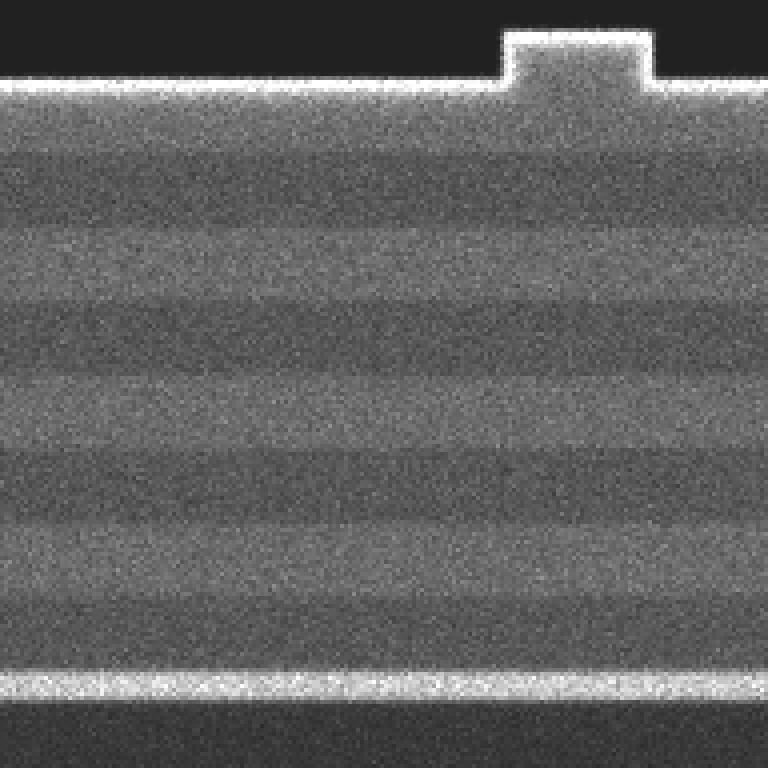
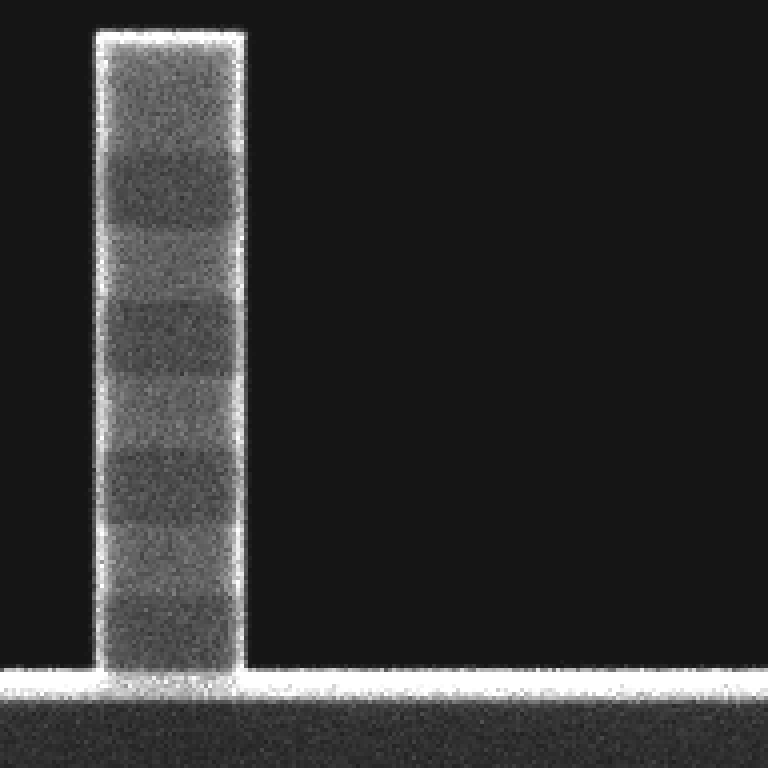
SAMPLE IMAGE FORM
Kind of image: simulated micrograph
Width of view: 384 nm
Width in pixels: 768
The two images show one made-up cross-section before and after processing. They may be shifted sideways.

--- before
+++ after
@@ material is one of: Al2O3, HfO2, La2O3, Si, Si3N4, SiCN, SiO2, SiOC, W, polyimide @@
Si3N4 and SiO2 removed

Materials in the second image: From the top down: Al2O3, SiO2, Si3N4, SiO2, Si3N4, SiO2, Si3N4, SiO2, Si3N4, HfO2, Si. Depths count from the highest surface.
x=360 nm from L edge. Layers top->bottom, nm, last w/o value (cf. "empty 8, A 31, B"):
empty 320, HfO2 14, Si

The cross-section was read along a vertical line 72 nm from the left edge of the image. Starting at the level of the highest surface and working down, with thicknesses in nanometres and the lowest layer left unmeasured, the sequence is Al2O3 24, SiO2 36, Si3N4 38, SiO2 36, Si3N4 38, SiO2 36, Si3N4 38, SiO2 36, Si3N4 38, HfO2 14, Si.